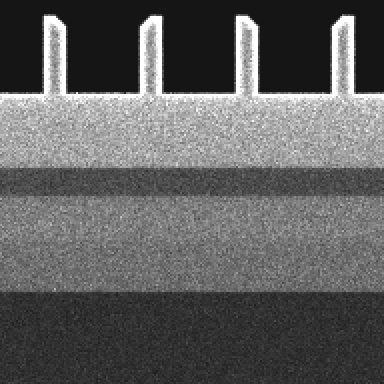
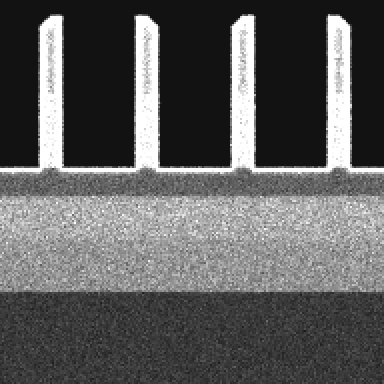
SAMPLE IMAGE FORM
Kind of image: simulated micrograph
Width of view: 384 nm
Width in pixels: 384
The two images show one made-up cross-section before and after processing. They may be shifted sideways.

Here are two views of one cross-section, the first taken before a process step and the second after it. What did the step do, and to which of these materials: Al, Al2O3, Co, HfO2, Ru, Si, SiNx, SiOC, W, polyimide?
It removed W.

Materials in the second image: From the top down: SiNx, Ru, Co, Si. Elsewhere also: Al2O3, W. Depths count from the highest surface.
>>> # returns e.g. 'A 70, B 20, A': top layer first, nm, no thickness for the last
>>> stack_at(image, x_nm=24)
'empty 152, SiNx 28, Ru 44, Co 52, Si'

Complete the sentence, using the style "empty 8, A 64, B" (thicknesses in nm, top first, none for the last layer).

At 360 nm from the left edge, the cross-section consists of empty 152, SiNx 28, Ru 44, Co 52, Si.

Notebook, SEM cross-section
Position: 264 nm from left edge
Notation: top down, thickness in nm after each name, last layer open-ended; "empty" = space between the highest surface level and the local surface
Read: empty 152, SiNx 28, Ru 44, Co 52, Si